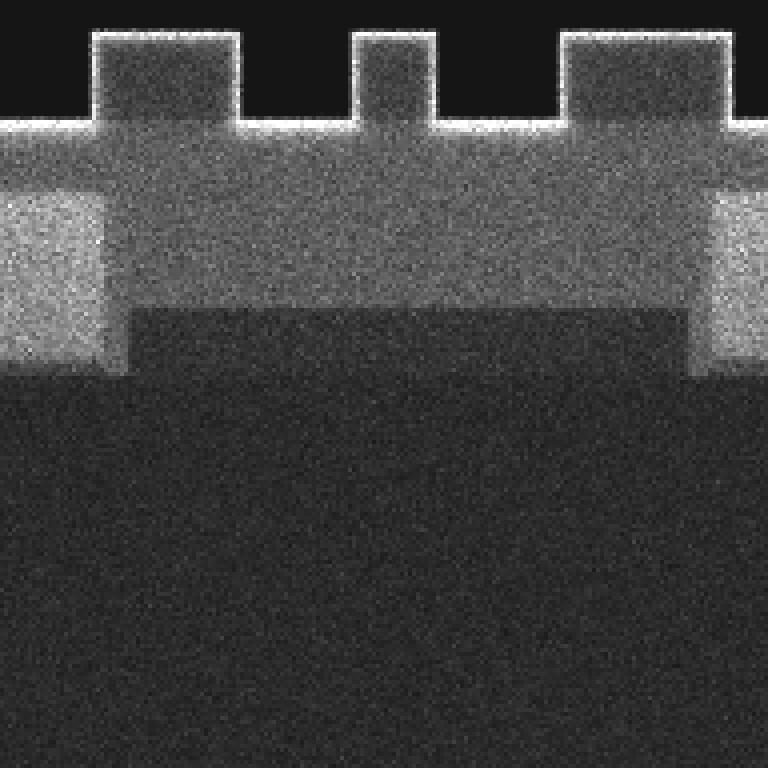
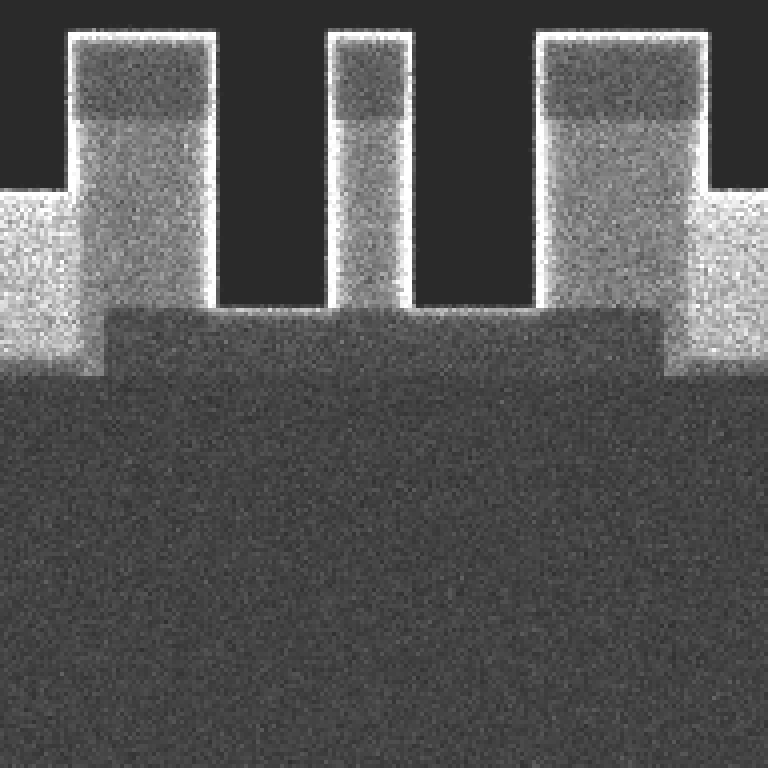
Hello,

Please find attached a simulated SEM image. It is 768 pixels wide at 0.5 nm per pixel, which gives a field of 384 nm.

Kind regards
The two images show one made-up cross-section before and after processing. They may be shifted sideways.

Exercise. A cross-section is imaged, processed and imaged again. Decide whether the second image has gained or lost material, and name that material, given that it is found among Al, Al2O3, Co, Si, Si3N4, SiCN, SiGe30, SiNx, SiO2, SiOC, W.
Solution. removed: SiO2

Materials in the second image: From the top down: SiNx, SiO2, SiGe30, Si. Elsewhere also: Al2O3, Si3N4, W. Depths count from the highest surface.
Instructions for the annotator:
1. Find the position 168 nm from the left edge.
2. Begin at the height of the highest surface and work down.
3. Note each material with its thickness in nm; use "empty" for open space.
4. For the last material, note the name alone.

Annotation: SiNx 44, SiO2 94, SiGe30 34, Si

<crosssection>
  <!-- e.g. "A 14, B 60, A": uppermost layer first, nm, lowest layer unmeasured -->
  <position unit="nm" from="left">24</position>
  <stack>empty 80, W 84, Si3N4 8, Si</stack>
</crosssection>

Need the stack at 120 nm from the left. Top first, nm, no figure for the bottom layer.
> empty 138, SiGe30 34, Si